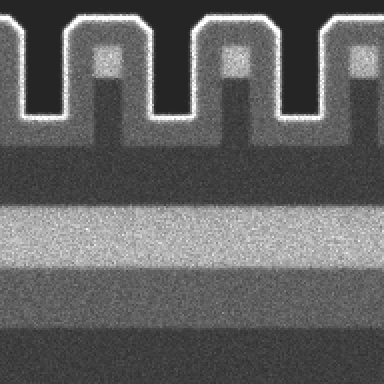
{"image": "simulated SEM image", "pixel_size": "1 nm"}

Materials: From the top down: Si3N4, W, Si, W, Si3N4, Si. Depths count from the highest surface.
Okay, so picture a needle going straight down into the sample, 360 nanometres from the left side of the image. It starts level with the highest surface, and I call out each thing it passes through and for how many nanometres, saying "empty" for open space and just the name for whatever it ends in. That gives Si3N4 30, W 32, Si 128, W 62, Si3N4 60, Si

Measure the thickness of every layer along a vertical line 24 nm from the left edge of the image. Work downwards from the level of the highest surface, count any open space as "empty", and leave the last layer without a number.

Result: empty 100, Si3N4 30, Si 60, W 62, Si3N4 60, Si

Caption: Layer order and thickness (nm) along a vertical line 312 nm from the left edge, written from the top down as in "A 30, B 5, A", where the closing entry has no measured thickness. empty 100, Si3N4 30, Si 60, W 62, Si3N4 60, Si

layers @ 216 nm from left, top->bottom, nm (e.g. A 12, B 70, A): Si3N4 130, Si 60, W 62, Si3N4 60, Si